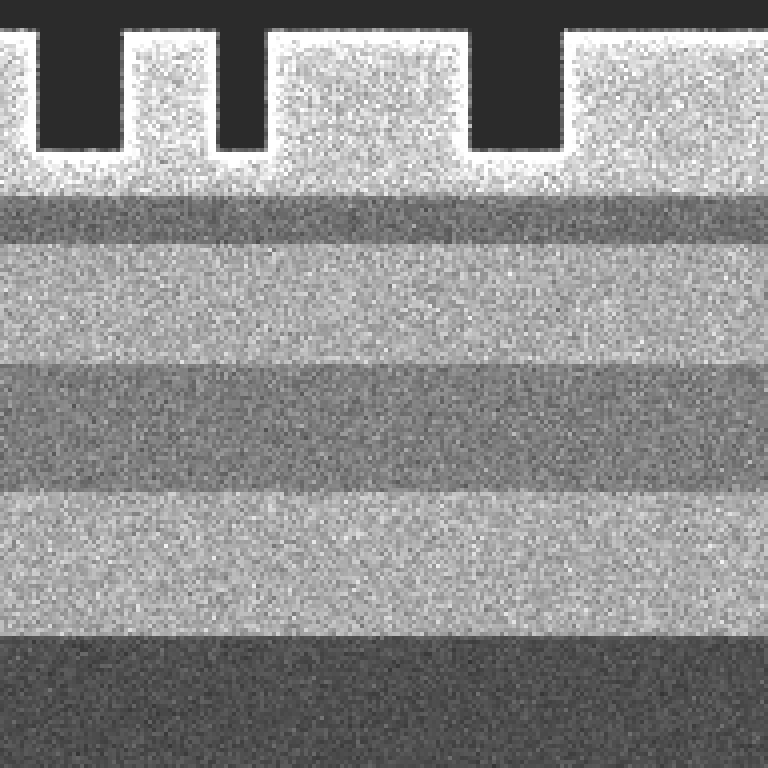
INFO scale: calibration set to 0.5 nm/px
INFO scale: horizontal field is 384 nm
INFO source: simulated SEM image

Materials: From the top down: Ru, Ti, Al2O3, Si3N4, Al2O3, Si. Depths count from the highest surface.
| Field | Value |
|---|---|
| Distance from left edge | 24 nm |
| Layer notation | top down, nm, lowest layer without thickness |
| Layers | empty 60, Ru 22, Ti 24, Al2O3 60, Si3N4 64, Al2O3 72, Si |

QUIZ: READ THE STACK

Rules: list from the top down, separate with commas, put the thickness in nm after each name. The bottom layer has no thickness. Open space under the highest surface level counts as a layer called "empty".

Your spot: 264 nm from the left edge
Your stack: empty 60, Ru 22, Ti 24, Al2O3 60, Si3N4 64, Al2O3 72, Si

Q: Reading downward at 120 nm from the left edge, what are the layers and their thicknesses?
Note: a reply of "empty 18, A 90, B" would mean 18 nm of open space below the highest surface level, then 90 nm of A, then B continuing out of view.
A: empty 60, Ru 22, Ti 24, Al2O3 60, Si3N4 64, Al2O3 72, Si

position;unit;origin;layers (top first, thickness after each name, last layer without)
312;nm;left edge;Ru 82, Ti 24, Al2O3 60, Si3N4 64, Al2O3 72, Si